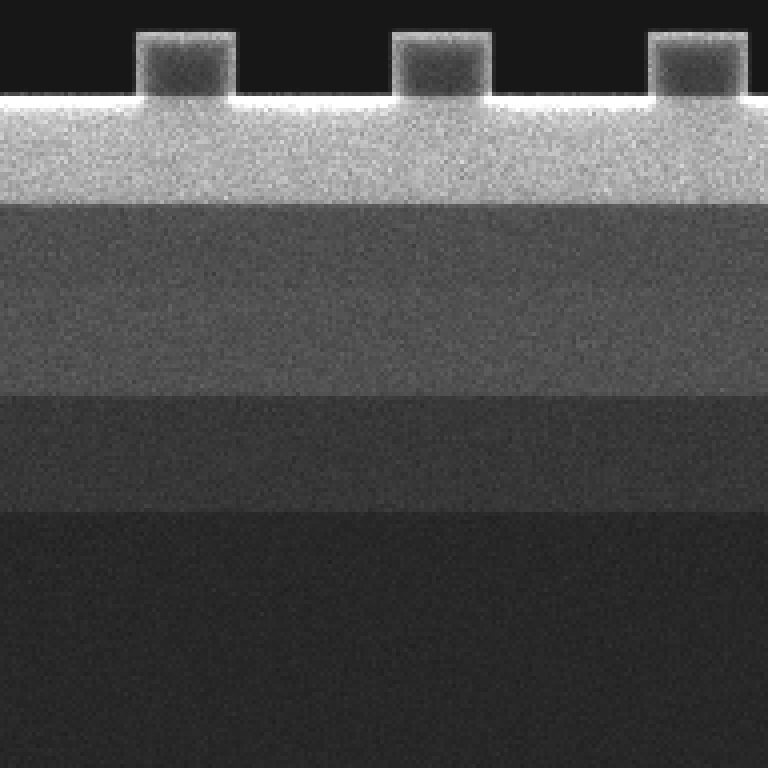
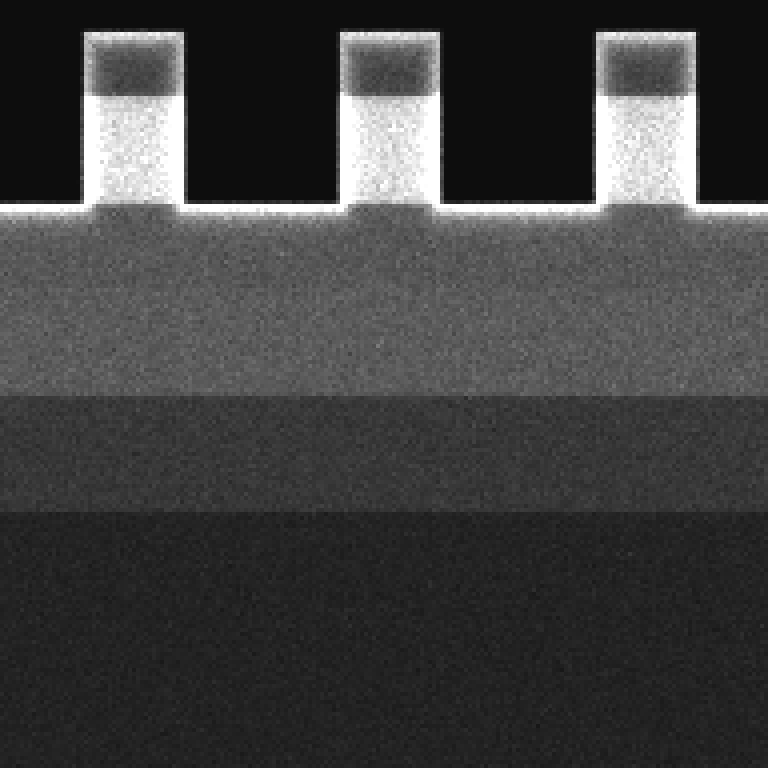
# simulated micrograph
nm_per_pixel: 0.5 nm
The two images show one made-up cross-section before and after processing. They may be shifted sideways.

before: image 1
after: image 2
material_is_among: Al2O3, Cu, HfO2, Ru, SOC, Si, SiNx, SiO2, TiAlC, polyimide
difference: HfO2, removed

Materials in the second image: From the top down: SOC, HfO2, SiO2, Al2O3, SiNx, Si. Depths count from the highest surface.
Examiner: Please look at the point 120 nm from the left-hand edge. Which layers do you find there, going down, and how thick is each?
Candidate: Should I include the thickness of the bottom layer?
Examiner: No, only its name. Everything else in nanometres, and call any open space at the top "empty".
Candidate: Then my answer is empty 86, SiO2 42, Al2O3 54, SiNx 58, Si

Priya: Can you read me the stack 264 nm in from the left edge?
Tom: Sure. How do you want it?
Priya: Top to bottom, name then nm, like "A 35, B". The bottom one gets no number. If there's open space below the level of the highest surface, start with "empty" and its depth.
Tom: empty 86, SiO2 42, Al2O3 54, SiNx 58, Si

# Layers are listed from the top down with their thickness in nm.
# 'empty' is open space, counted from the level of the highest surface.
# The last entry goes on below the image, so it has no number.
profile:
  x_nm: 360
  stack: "empty 86, SiO2 42, Al2O3 54, SiNx 58, Si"